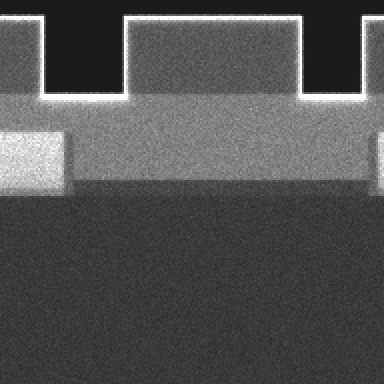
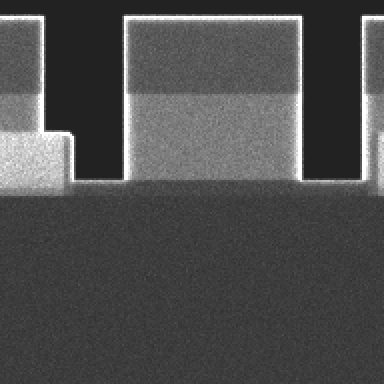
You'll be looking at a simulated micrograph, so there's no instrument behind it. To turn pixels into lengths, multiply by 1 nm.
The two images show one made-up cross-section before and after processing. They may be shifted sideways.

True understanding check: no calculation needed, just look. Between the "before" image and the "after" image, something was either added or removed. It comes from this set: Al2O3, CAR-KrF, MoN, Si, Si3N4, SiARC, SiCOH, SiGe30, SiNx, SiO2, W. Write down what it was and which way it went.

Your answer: SiO2 (removed)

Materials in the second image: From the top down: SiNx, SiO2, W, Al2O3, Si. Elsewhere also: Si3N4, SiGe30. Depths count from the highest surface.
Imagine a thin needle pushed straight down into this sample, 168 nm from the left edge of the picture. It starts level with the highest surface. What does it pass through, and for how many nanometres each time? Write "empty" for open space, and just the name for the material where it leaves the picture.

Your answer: SiNx 78, SiO2 86, SiGe30 16, Si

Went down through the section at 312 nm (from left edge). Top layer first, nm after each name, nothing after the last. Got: empty 164, SiGe30 16, Si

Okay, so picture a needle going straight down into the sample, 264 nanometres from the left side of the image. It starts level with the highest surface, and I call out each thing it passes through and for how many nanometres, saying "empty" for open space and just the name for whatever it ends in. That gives SiNx 78, SiO2 86, SiGe30 16, Si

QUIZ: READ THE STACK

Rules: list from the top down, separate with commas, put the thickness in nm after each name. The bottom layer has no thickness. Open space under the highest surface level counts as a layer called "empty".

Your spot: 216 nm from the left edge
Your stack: SiNx 78, SiO2 86, SiGe30 16, Si